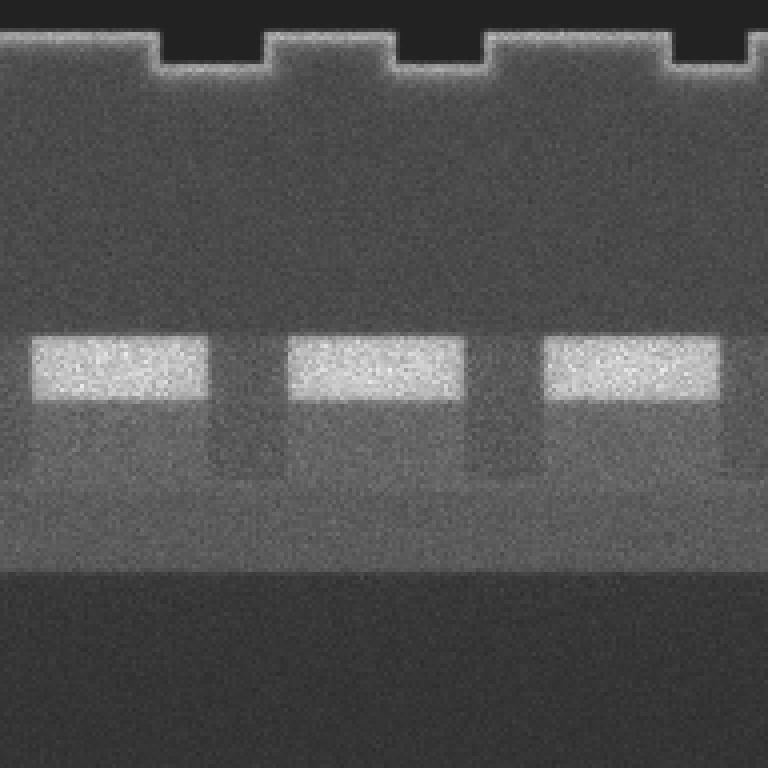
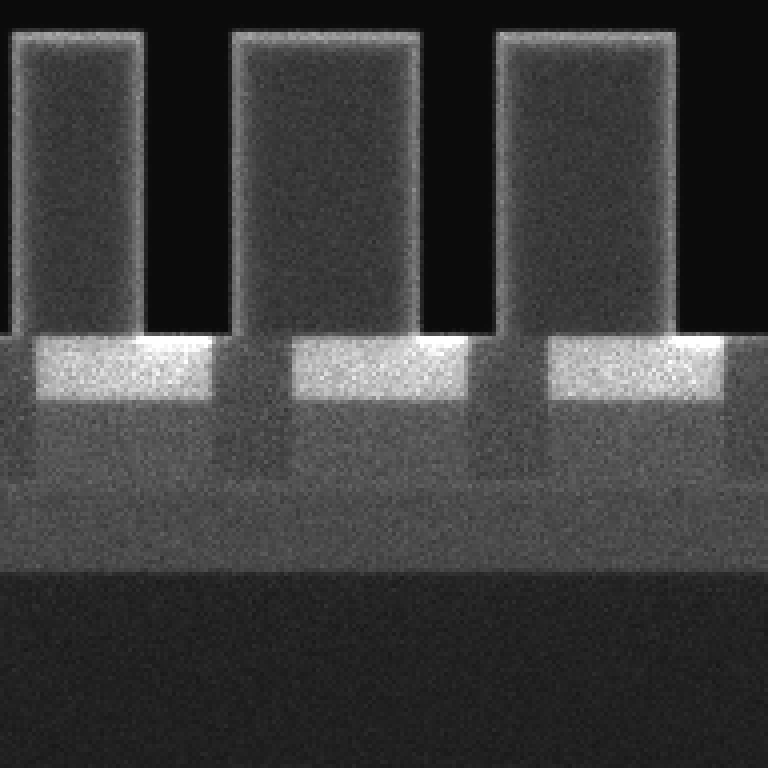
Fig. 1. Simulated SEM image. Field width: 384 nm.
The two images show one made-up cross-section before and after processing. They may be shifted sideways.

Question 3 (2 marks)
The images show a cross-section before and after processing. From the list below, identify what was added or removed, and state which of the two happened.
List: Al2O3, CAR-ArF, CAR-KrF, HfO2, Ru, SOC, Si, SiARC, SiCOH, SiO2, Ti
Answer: SOC was removed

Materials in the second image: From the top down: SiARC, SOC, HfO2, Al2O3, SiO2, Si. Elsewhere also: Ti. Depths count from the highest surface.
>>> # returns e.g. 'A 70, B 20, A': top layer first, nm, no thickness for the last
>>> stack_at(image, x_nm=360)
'empty 152, HfO2 32, Al2O3 46, SiO2 40, Si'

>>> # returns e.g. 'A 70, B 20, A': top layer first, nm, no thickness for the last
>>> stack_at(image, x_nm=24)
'SiARC 16, SOC 136, HfO2 32, Al2O3 46, SiO2 40, Si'